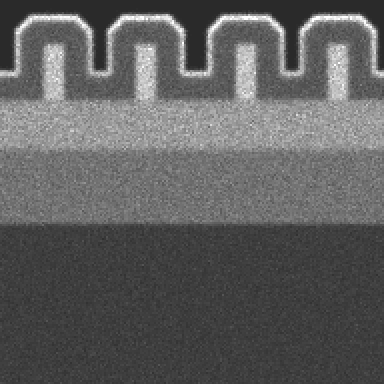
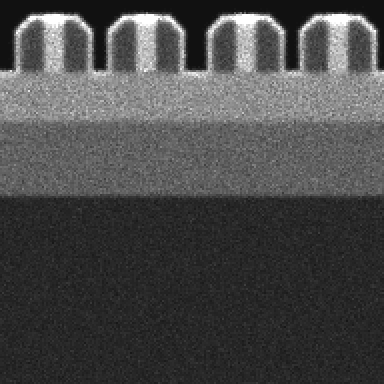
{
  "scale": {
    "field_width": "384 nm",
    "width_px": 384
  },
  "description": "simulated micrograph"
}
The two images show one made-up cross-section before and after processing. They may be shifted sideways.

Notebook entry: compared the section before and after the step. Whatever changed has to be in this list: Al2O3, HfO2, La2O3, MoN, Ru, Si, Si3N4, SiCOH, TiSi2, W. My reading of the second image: Si3N4 removed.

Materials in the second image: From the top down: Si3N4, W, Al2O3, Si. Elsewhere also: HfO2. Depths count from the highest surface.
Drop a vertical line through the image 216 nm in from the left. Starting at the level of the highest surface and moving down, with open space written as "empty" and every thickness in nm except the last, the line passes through empty 6, Si3N4 50, W 50, Al2O3 74, Si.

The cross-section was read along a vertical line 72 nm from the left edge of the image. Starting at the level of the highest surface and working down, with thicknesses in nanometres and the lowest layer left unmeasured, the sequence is Si3N4 56, W 50, Al2O3 74, Si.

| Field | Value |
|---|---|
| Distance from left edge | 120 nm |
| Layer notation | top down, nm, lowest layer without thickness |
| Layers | empty 2, Si3N4 54, W 50, Al2O3 74, Si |